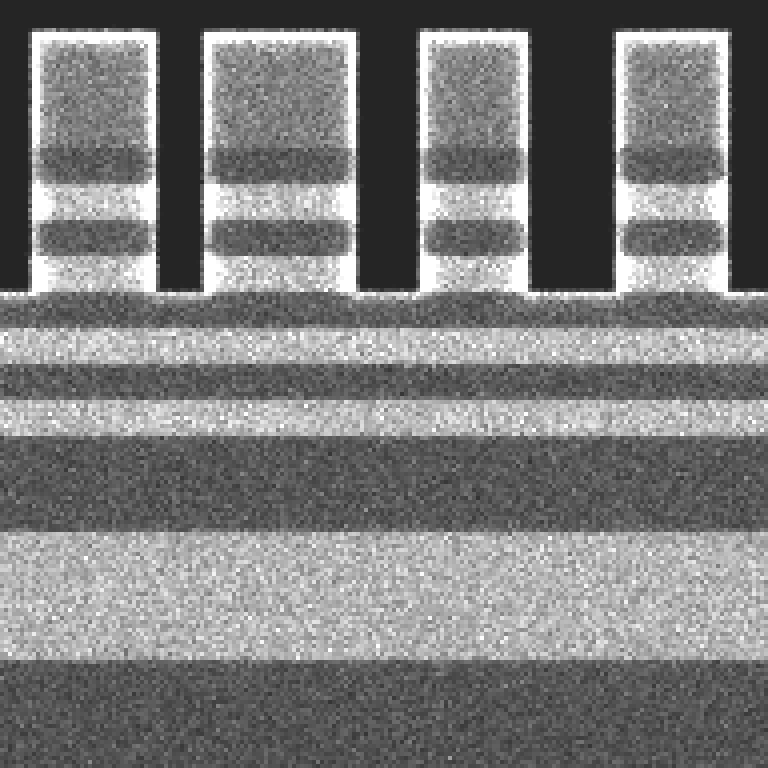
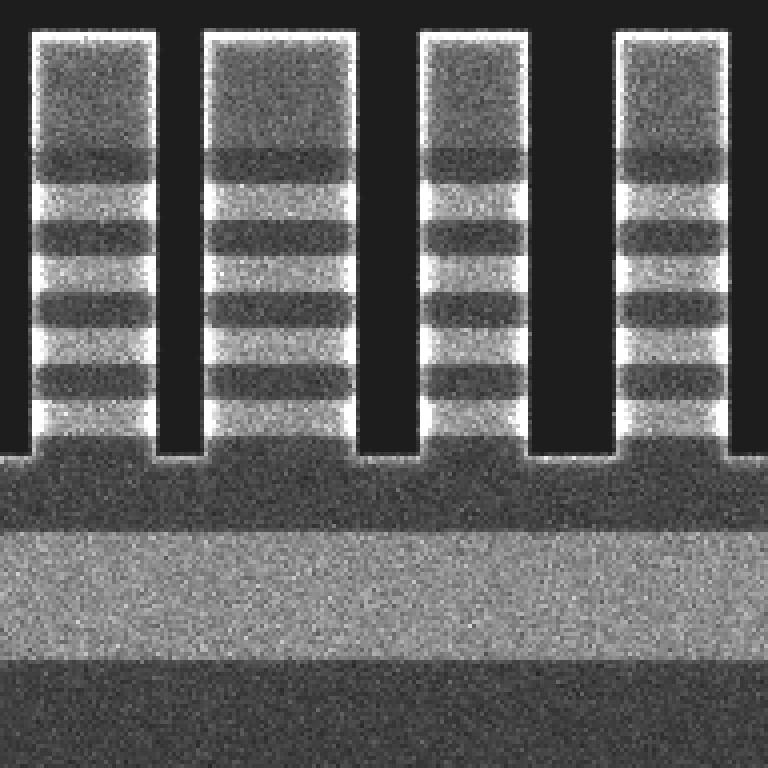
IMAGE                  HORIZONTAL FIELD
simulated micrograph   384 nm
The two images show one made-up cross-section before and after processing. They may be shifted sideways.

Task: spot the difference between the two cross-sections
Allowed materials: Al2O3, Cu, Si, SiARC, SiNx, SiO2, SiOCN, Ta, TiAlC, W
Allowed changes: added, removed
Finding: removed Al2O3 and Si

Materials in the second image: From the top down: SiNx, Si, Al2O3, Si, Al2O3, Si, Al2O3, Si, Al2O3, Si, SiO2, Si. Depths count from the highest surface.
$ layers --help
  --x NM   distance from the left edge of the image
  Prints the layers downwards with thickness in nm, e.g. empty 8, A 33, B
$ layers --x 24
SiNx 58, Si 18, Al2O3 18, Si 18, Al2O3 18, Si 18, Al2O3 18, Si 18, Al2O3 18, Si 48, SiO2 64, Si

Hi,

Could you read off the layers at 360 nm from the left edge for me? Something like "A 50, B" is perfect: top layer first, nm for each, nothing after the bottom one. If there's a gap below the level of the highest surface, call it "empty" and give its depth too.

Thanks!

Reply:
SiNx 58, Si 18, Al2O3 18, Si 18, Al2O3 18, Si 18, Al2O3 18, Si 18, Al2O3 18, Si 48, SiO2 64, Si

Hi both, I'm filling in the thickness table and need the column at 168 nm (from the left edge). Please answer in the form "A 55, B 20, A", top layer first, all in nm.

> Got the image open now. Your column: SiNx 58, Si 18, Al2O3 18, Si 18, Al2O3 18, Si 18, Al2O3 18, Si 18, Al2O3 18, Si 48, SiO2 64, Si